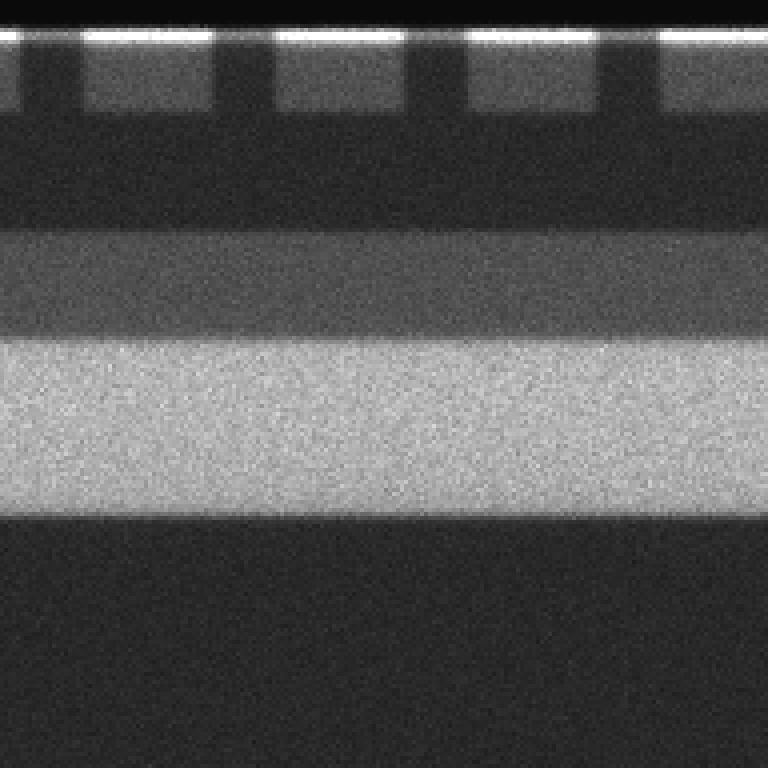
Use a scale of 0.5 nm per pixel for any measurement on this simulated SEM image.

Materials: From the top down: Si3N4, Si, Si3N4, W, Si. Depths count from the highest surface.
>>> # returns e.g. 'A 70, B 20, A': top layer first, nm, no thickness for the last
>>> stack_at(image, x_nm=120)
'Si 100, Si3N4 54, W 88, Si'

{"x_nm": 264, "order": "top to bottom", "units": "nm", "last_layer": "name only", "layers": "Si3N4 40, Si 60, Si3N4 54, W 88, Si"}